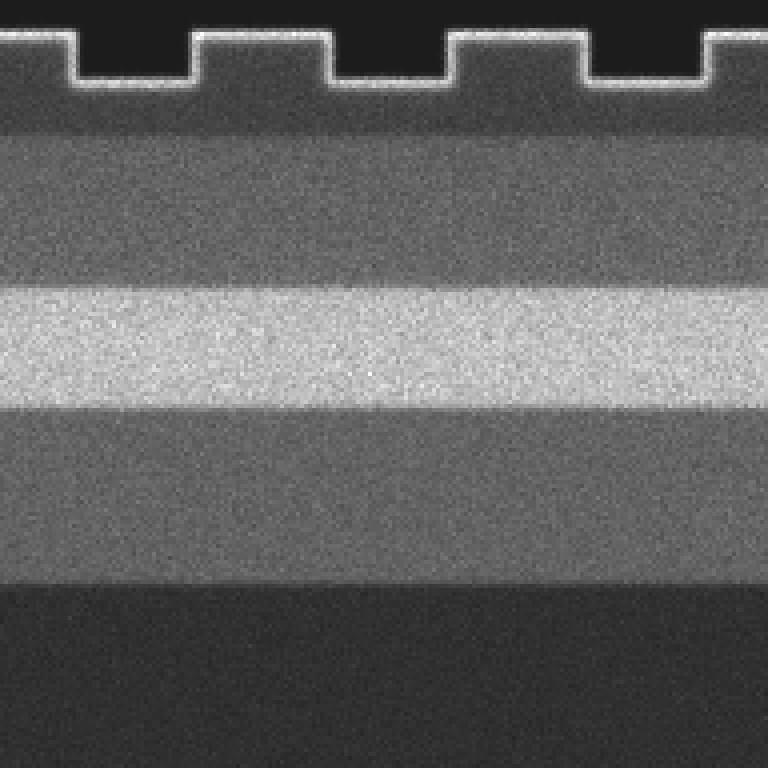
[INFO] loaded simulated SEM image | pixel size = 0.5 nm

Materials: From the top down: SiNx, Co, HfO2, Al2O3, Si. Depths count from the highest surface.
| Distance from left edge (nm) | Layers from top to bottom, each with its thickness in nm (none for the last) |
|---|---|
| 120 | SiNx 52, Co 76, HfO2 60, Al2O3 88, Si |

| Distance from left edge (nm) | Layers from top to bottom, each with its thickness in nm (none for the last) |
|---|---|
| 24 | SiNx 52, Co 76, HfO2 60, Al2O3 88, Si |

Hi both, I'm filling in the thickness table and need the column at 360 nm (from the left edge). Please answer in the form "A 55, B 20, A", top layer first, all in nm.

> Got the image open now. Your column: SiNx 52, Co 76, HfO2 60, Al2O3 88, Si